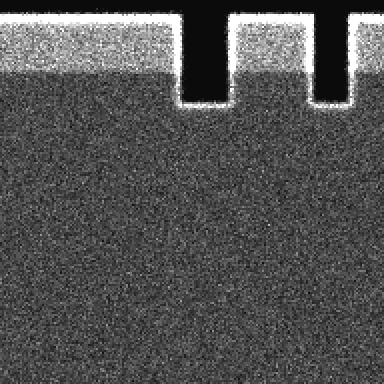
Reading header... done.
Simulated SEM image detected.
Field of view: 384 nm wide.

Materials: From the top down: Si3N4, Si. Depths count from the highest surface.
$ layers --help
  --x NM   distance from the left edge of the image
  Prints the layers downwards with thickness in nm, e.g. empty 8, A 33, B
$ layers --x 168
Si3N4 56, Si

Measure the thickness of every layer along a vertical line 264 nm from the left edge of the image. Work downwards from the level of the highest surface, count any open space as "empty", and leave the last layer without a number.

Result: Si3N4 56, Si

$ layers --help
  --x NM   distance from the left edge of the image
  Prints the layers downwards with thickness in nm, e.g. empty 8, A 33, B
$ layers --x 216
empty 88, Si